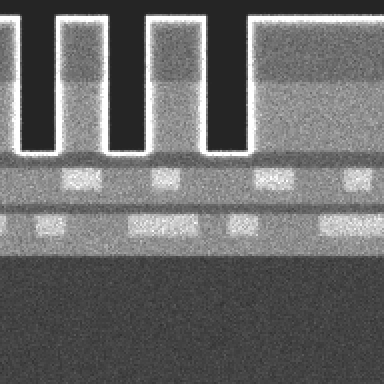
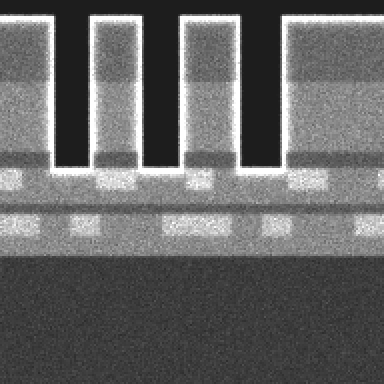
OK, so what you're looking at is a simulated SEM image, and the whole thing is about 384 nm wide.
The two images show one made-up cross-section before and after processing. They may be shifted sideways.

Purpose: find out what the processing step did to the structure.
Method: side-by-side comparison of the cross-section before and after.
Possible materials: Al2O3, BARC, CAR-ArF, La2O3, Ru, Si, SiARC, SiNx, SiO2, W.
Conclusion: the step removed SiNx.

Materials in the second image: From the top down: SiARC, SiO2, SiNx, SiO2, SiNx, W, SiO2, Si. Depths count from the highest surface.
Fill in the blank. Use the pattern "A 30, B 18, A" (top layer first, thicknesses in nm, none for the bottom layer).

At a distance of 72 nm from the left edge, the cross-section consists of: empty 152, SiO2 36, SiNx 10, W 22, SiO2 20, Si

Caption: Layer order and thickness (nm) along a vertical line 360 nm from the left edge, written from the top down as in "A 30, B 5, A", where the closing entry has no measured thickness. SiARC 66, SiO2 70, SiNx 16, SiO2 36, SiNx 10, W 22, SiO2 20, Si